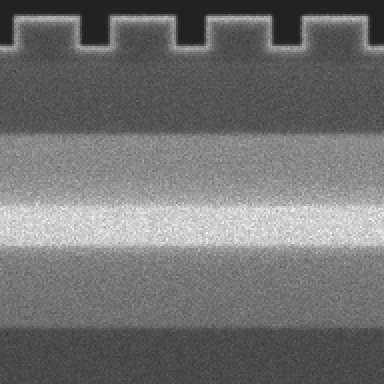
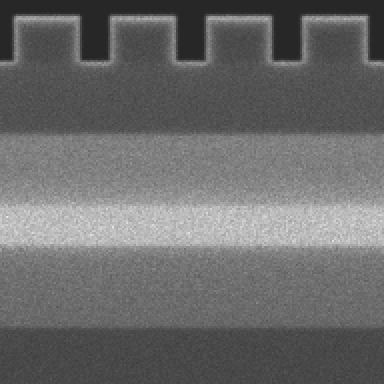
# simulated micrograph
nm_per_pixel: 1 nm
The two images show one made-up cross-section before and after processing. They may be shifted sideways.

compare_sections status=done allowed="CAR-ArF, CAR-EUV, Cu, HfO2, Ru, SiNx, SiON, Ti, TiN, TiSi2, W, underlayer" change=removed material="underlayer"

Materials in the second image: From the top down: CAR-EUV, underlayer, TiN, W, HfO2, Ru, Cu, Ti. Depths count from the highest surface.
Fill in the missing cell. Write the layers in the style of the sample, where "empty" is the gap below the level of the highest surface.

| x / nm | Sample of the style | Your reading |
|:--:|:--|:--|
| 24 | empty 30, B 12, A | CAR-EUV 30, underlayer 16, TiN 72, W 72, HfO2 40, Ru 8, Cu 74, Ti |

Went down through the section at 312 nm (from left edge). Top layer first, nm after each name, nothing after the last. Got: CAR-EUV 30, underlayer 16, TiN 72, W 72, HfO2 40, Ru 8, Cu 74, Ti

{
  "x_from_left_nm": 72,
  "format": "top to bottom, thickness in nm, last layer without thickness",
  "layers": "CAR-EUV 30, underlayer 16, TiN 72, W 72, HfO2 40, Ru 8, Cu 74, Ti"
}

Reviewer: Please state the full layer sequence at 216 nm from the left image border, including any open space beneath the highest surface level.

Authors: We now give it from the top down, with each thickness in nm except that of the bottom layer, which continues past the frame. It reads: CAR-EUV 30, underlayer 16, TiN 72, W 72, HfO2 40, Ru 8, Cu 74, Ti